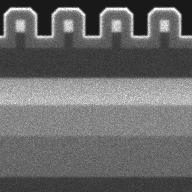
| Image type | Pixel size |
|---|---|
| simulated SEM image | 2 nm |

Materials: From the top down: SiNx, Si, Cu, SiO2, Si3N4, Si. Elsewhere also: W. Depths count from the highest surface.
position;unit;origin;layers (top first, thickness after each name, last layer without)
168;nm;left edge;empty 12, SiNx 68, Si 60, Cu 54, SiO2 62, Si3N4 82, Si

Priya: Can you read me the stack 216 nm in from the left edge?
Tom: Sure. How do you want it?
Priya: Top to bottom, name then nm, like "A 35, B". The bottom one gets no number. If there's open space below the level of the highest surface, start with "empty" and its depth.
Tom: SiNx 80, Si 60, Cu 54, SiO2 62, Si3N4 82, Si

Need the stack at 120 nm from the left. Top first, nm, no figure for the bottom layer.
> SiNx 80, Si 60, Cu 54, SiO2 62, Si3N4 82, Si